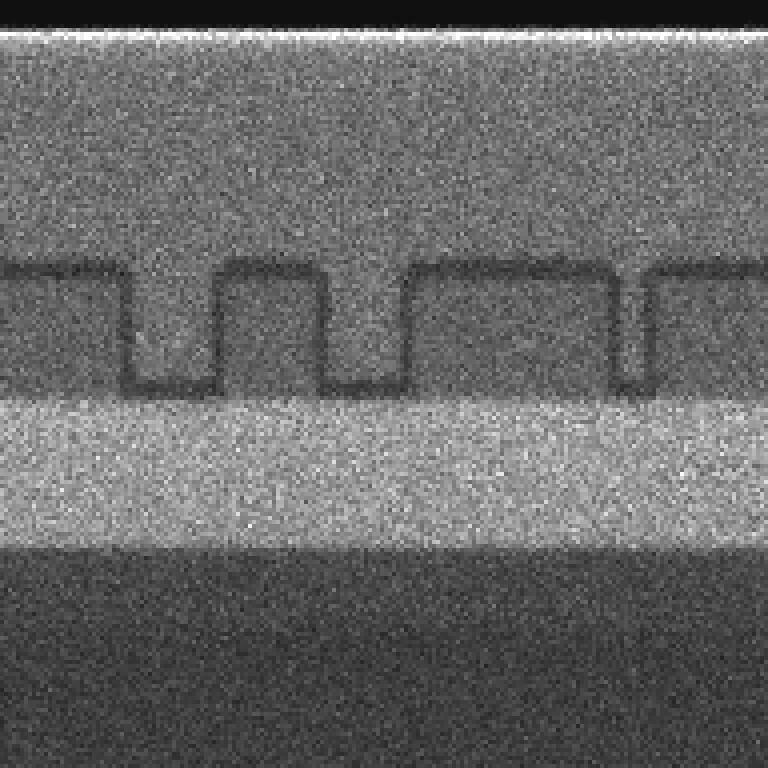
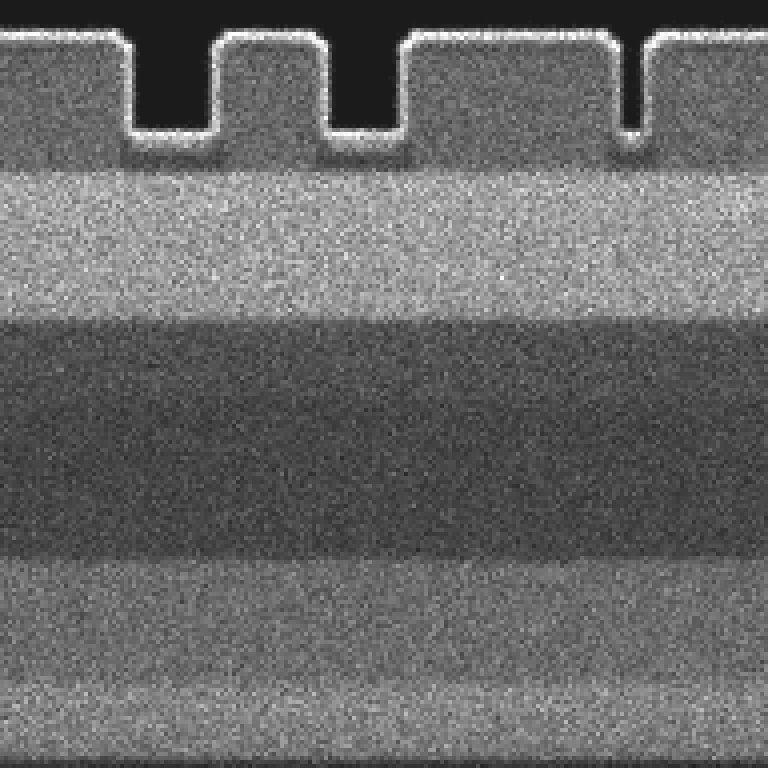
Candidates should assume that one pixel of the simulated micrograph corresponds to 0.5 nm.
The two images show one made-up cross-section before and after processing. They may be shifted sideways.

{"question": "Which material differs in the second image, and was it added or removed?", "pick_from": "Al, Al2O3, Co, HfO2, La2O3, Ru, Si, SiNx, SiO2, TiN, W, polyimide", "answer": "Co, removed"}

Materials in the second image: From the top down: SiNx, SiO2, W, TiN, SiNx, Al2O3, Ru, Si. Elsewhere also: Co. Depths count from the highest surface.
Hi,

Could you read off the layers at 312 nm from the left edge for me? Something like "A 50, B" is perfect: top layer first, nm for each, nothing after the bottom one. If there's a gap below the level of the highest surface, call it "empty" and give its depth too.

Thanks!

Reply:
empty 50, Co 10, SiNx 10, W 74, TiN 40, SiNx 80, Al2O3 62, Ru 38, Si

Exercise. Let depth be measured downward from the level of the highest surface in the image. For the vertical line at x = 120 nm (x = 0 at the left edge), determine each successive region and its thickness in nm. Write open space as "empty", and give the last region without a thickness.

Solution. SiNx 10, SiO2 60, W 74, TiN 40, SiNx 80, Al2O3 62, Ru 38, Si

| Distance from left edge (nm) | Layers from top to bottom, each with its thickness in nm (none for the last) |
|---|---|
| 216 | SiNx 10, SiO2 60, W 74, TiN 40, SiNx 80, Al2O3 62, Ru 38, Si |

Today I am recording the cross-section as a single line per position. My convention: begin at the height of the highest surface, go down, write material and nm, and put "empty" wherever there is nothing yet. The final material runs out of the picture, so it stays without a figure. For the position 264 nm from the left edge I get SiNx 10, SiO2 60, W 74, TiN 40, SiNx 80, Al2O3 62, Ru 38, Si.